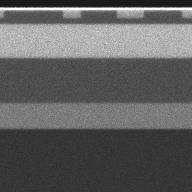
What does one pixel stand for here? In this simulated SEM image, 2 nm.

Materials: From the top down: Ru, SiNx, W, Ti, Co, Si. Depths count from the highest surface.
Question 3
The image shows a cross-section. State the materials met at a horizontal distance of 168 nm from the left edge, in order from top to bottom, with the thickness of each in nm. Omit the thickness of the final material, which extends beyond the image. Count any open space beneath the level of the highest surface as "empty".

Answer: SiNx 32, W 68, Ti 90, Co 52, Si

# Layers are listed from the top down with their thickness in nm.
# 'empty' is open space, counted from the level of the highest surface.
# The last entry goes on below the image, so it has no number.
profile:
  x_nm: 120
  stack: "SiNx 32, W 68, Ti 90, Co 52, Si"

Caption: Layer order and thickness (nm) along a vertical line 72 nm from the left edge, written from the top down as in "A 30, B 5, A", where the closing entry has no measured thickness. SiNx 32, W 68, Ti 90, Co 52, Si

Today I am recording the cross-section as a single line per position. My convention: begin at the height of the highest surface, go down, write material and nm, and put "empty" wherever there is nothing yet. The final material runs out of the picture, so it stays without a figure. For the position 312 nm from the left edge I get SiNx 32, W 68, Ti 90, Co 52, Si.